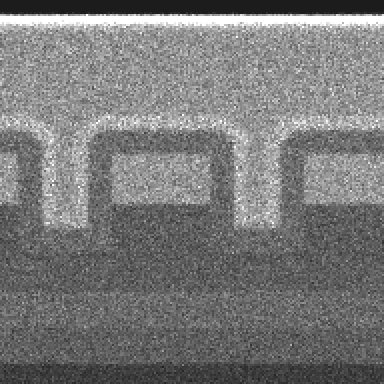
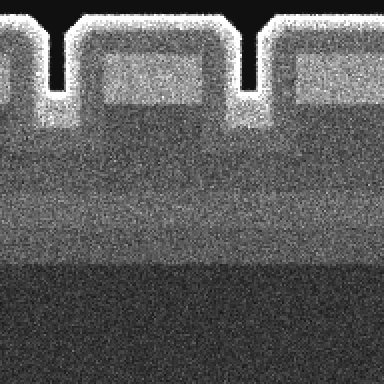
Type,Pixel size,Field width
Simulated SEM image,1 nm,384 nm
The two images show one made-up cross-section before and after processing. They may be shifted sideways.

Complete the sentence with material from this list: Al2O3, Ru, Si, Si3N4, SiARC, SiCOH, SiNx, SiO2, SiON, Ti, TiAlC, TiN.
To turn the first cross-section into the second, SiO2 must be removed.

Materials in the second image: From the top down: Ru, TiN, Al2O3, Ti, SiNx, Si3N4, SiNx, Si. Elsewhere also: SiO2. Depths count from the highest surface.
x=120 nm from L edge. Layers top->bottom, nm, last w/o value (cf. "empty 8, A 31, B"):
Ru 14, TiN 24, Al2O3 50, Ti 58, SiNx 30, Si3N4 36, SiNx 36, Si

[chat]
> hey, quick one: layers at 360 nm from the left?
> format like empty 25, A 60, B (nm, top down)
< Ru 14, TiN 24, Al2O3 50, Ti 58, SiNx 30, Si3N4 36, SiNx 36, Si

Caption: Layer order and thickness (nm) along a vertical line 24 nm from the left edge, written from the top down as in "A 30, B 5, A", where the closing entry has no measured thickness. Ru 18, TiN 118, Ti 10, SiNx 30, Si3N4 36, SiNx 36, Si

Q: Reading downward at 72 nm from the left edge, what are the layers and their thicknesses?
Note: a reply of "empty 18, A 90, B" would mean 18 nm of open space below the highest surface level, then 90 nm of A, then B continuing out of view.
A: empty 12, Ru 100, TiN 24, Ti 10, SiNx 30, Si3N4 36, SiNx 36, Si